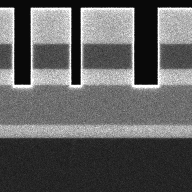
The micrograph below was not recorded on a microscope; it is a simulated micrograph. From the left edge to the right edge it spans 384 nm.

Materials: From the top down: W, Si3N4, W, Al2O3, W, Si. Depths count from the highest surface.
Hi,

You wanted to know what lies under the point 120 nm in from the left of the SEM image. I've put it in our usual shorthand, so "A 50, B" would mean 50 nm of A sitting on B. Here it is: W 72, Si3N4 50, W 32, Al2O3 80, W 26, Si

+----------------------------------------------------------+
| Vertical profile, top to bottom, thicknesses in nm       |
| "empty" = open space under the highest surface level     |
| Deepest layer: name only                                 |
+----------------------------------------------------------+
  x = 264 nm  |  W 72, Si3N4 50, W 32, Al2O3 80, W 26, Si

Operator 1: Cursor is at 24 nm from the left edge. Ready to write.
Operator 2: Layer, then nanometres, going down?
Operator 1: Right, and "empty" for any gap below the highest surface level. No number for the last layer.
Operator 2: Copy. W 72, Si3N4 50, W 32, Al2O3 80, W 26, Si